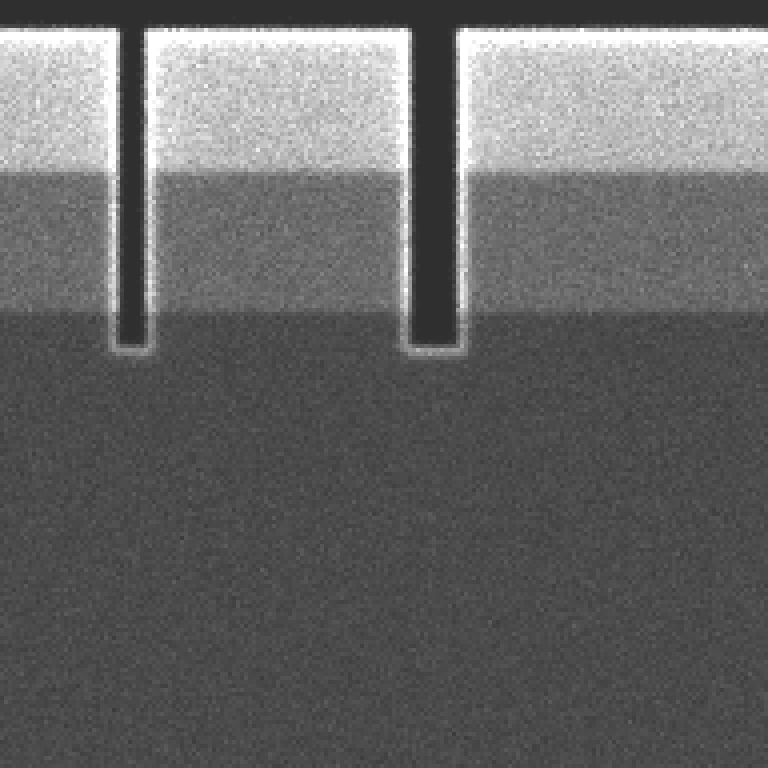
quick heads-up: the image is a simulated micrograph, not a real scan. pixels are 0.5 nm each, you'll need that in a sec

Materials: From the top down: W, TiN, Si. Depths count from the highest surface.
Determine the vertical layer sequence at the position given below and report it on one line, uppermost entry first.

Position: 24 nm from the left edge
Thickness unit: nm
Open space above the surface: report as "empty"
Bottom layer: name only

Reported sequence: W 70, TiN 70, Si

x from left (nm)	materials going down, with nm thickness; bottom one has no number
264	W 70, TiN 70, Si